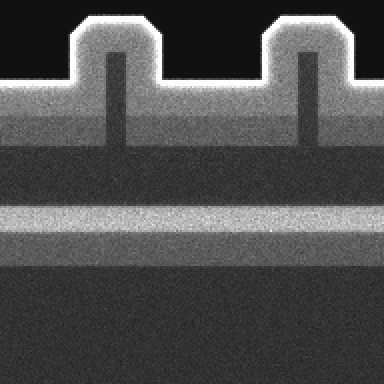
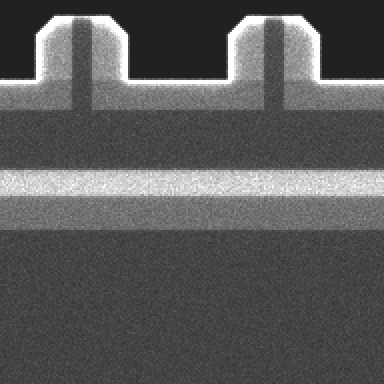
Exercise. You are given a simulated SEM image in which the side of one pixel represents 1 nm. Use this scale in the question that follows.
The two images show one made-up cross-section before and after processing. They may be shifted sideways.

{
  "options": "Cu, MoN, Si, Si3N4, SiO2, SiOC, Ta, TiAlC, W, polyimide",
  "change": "removed",
  "material": "SiO2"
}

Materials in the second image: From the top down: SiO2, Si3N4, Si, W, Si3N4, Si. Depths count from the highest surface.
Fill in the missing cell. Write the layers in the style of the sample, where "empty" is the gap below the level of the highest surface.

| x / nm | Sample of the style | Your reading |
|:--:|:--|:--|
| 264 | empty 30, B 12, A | Si 154, W 26, Si3N4 34, Si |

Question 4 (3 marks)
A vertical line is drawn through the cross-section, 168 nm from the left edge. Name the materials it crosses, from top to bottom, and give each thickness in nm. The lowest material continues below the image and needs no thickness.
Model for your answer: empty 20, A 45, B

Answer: empty 64, Si3N4 30, Si 60, W 26, Si3N4 34, Si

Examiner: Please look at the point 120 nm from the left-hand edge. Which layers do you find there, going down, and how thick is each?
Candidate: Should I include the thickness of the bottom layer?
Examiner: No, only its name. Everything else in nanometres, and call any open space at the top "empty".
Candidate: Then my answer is empty 12, SiO2 52, Si3N4 30, Si 60, W 26, Si3N4 34, Si